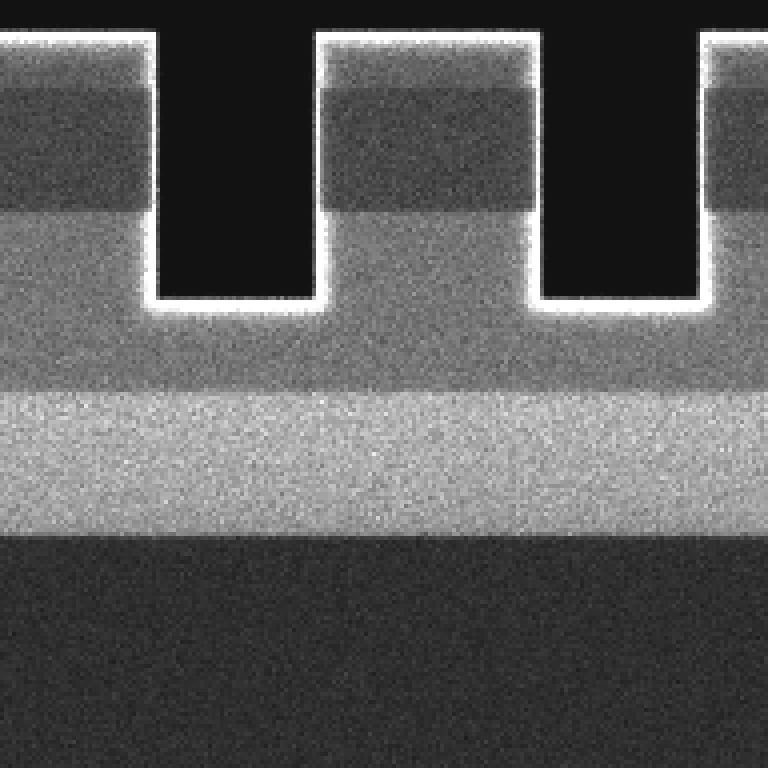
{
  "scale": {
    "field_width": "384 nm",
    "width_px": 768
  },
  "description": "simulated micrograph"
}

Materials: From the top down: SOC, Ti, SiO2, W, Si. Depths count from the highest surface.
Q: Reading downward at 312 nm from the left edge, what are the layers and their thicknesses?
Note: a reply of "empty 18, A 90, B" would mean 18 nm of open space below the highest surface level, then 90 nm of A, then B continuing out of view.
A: empty 134, SiO2 46, W 72, Si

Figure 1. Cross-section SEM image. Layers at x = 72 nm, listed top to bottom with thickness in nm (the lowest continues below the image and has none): SOC 28, Ti 62, SiO2 90, W 72, Si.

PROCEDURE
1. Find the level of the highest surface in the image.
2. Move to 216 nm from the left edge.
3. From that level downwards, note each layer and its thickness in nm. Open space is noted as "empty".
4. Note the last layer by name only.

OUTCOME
SOC 28, Ti 62, SiO2 90, W 72, Si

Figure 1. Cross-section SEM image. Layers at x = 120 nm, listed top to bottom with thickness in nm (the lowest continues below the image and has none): empty 134, SiO2 46, W 72, Si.